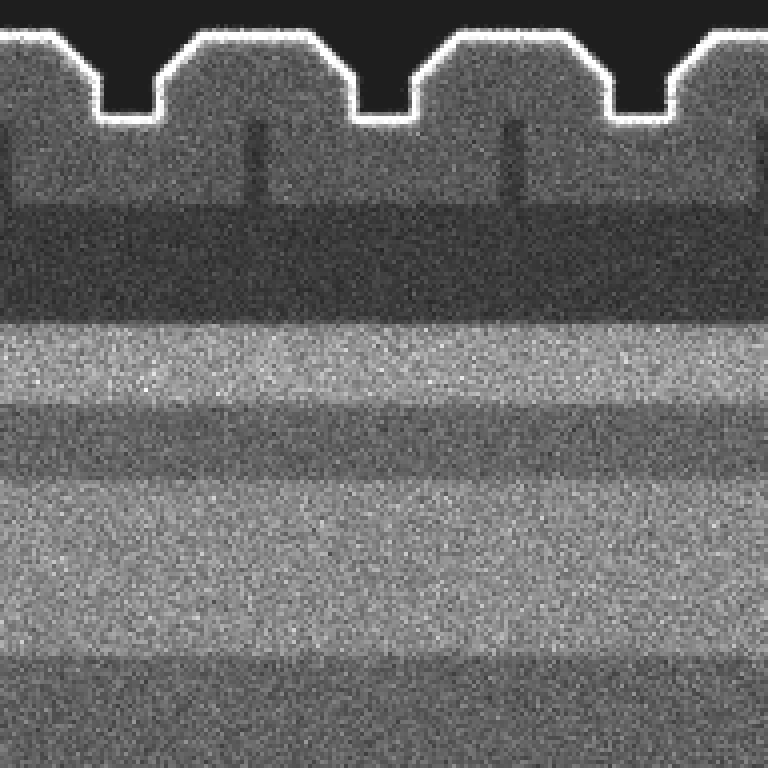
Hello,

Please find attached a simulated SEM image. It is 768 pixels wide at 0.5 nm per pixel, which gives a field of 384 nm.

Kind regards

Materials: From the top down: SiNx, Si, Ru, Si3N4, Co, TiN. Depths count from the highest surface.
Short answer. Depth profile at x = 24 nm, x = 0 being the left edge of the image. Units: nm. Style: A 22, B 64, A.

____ SiNx 86, Si 60, Ru 40, Si3N4 38, Co 88, TiN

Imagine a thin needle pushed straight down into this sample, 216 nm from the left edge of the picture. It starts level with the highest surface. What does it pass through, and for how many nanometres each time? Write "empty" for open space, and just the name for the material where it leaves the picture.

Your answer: empty 12, SiNx 74, Si 60, Ru 40, Si3N4 38, Co 88, TiN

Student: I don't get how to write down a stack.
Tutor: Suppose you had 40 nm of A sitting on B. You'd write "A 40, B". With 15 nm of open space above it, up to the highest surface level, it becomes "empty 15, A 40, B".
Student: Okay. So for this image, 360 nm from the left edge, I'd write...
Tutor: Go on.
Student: SiNx 86, Si 60, Ru 40, Si3N4 38, Co 88, TiN